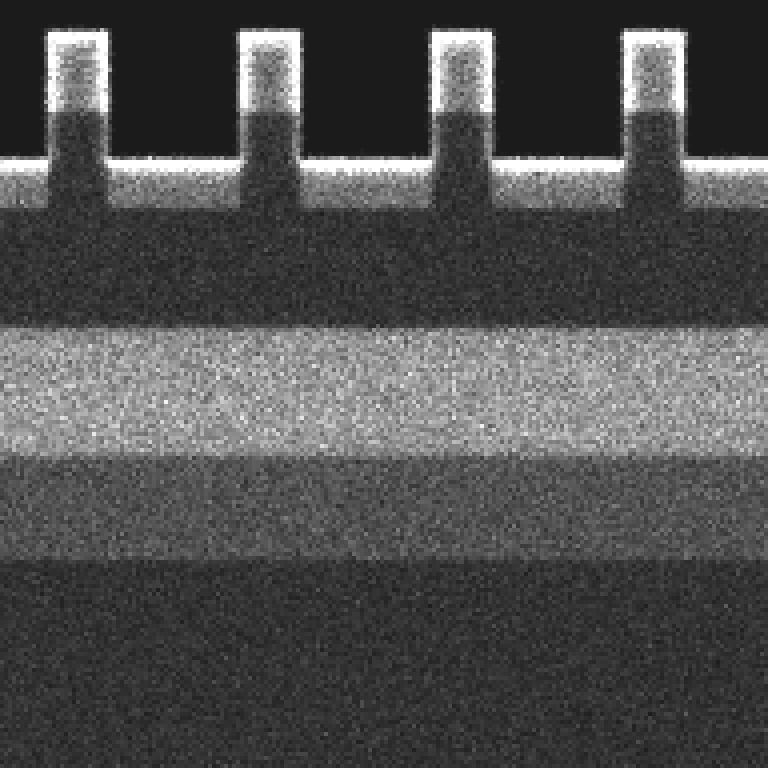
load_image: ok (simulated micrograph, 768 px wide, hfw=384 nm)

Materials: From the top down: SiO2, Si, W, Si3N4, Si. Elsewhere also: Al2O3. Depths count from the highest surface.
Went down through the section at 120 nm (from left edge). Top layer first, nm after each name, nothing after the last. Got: SiO2 40, Si 108, W 64, Si3N4 52, Si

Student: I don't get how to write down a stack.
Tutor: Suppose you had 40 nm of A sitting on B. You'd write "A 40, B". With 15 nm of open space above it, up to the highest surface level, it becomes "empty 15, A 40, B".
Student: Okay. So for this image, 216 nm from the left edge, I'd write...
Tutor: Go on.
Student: SiO2 40, Si 108, W 64, Si3N4 52, Si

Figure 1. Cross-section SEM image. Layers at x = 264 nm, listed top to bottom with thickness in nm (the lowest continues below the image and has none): empty 64, Al2O3 24, Si 60, W 64, Si3N4 52, Si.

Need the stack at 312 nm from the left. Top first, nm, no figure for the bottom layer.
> SiO2 40, Si 108, W 64, Si3N4 52, Si